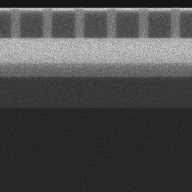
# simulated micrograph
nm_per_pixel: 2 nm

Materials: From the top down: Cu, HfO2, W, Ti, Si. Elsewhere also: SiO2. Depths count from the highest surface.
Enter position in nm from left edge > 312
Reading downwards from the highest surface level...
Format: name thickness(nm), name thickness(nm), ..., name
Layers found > SiO2 60, HfO2 50, W 28, Ti 62, Si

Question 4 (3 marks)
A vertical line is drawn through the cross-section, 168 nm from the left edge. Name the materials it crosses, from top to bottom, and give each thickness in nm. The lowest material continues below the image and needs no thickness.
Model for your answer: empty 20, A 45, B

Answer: SiO2 60, HfO2 50, W 28, Ti 62, Si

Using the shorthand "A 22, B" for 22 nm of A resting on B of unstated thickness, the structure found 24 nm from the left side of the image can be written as Cu 60, HfO2 50, W 28, Ti 62, Si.